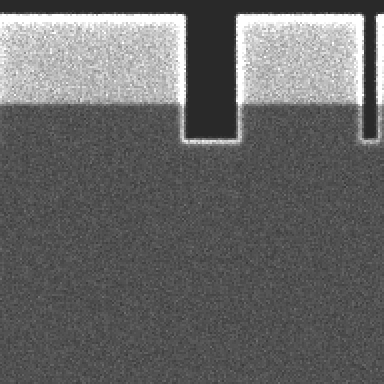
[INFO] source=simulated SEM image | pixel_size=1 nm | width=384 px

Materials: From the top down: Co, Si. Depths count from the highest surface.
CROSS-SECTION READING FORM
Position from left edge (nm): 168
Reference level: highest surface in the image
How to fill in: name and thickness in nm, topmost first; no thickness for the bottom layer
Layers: Co 88, Si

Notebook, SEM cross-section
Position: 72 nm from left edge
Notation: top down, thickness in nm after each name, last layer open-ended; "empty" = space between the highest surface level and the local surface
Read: Co 88, Si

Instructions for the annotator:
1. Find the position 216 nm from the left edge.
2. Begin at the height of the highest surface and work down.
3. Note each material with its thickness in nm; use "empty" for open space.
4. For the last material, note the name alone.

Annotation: empty 124, Si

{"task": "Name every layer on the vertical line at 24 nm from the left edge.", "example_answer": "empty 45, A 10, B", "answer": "Co 88, Si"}